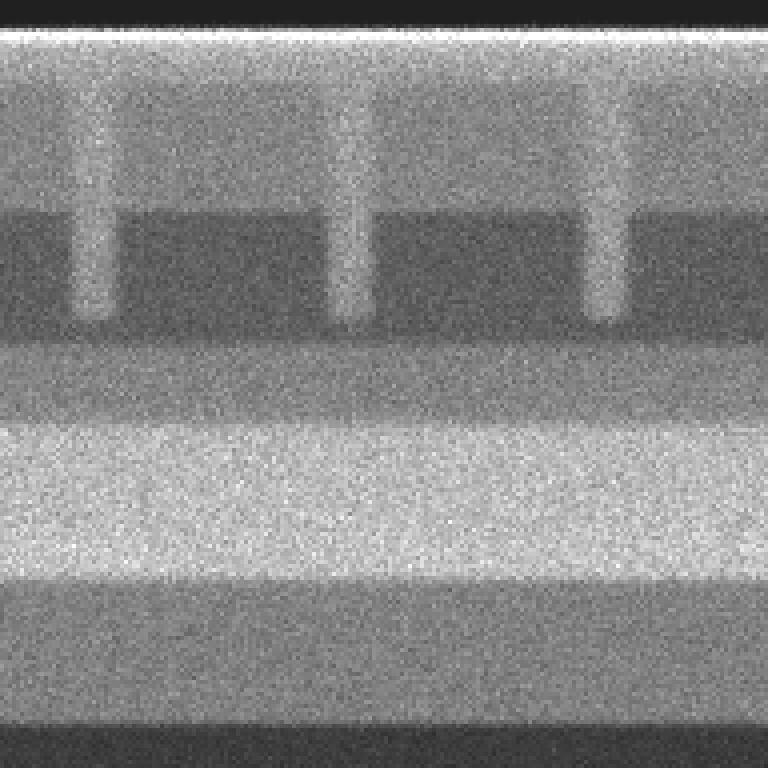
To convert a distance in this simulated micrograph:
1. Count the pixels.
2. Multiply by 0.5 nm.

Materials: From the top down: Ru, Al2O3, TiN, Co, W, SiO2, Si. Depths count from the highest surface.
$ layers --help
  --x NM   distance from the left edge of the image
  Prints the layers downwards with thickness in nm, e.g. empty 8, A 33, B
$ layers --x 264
Ru 26, Al2O3 64, TiN 66, Co 40, W 78, SiO2 72, Si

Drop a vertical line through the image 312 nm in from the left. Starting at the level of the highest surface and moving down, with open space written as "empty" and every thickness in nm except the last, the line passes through Ru 144, TiN 12, Co 40, W 78, SiO2 72, Si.